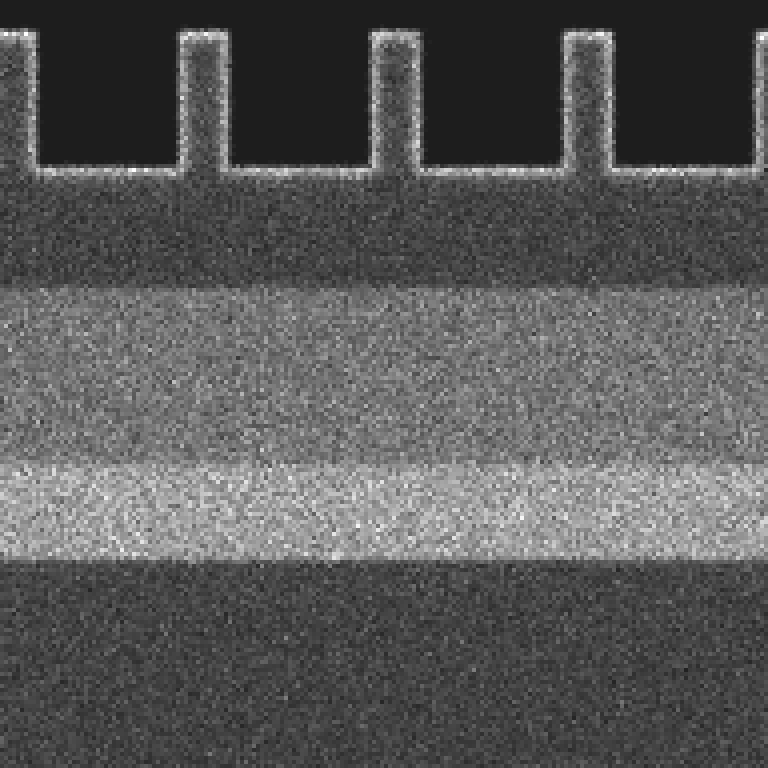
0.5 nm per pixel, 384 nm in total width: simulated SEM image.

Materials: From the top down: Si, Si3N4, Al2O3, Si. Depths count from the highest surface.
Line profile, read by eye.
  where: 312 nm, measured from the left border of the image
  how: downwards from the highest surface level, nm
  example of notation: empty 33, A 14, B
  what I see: empty 68, Si 60, Si3N4 88, Al2O3 48, Si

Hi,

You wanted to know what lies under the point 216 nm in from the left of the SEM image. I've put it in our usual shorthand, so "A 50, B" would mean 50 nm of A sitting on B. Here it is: empty 68, Si 60, Si3N4 88, Al2O3 48, Si